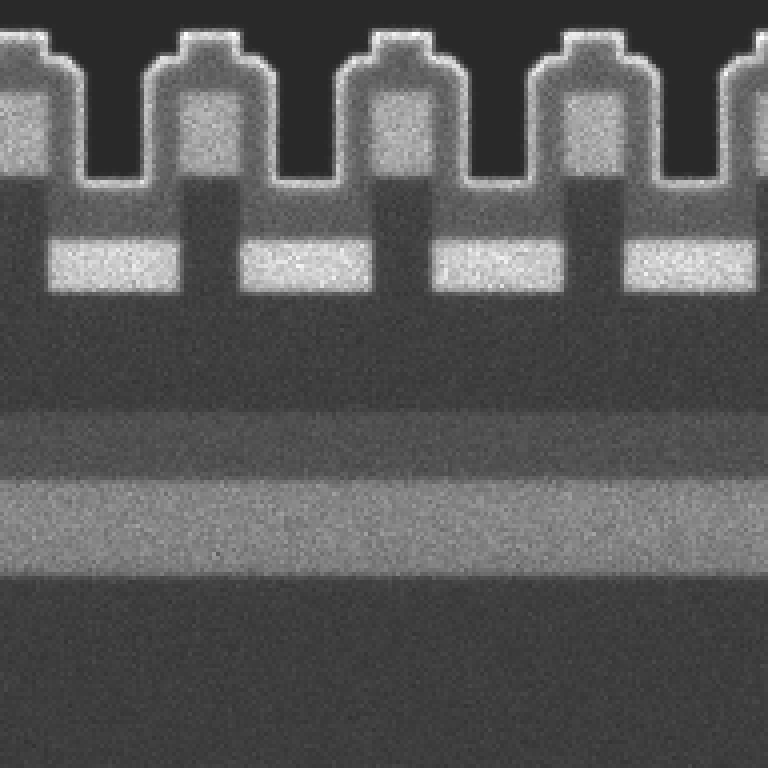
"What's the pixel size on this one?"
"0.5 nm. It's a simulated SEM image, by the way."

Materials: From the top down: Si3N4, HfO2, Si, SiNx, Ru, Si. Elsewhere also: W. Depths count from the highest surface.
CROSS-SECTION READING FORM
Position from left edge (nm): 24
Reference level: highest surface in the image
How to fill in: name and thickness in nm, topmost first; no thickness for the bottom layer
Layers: empty 12, Si3N4 92, HfO2 26, Si 60, SiNx 34, Ru 48, Si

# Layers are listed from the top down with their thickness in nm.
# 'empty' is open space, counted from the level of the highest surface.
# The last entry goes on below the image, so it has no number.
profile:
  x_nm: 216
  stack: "empty 12, Si3N4 92, HfO2 26, Si 60, SiNx 34, Ru 48, Si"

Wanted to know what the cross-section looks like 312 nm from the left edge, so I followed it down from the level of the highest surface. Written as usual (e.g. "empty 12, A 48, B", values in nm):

empty 12, Si3N4 92, HfO2 26, Si 60, SiNx 34, Ru 48, Si